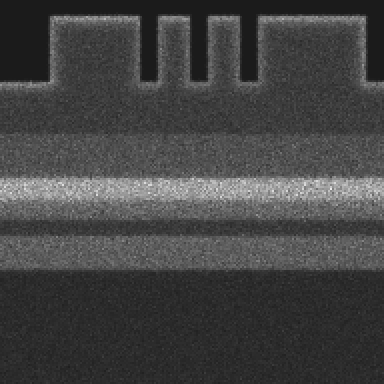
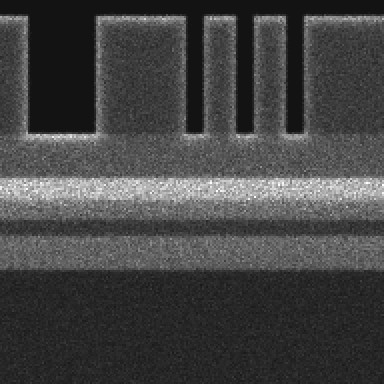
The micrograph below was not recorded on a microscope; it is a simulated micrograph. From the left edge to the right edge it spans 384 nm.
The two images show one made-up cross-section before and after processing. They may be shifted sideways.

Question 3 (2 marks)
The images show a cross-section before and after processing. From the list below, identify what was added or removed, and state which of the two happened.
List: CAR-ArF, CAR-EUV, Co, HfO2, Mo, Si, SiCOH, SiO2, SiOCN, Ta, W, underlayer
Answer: underlayer was removed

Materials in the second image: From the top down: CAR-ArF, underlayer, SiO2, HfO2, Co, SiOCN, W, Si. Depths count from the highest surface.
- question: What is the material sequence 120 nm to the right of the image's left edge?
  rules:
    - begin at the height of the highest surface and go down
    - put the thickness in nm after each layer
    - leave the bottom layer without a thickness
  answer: CAR-ArF 66, underlayer 52, SiO2 44, HfO2 22, Co 20, SiOCN 16, W 34, Si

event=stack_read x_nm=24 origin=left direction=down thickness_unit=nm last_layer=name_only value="CAR-ArF 66, underlayer 52, SiO2 44, HfO2 22, Co 20, SiOCN 16, W 34, Si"